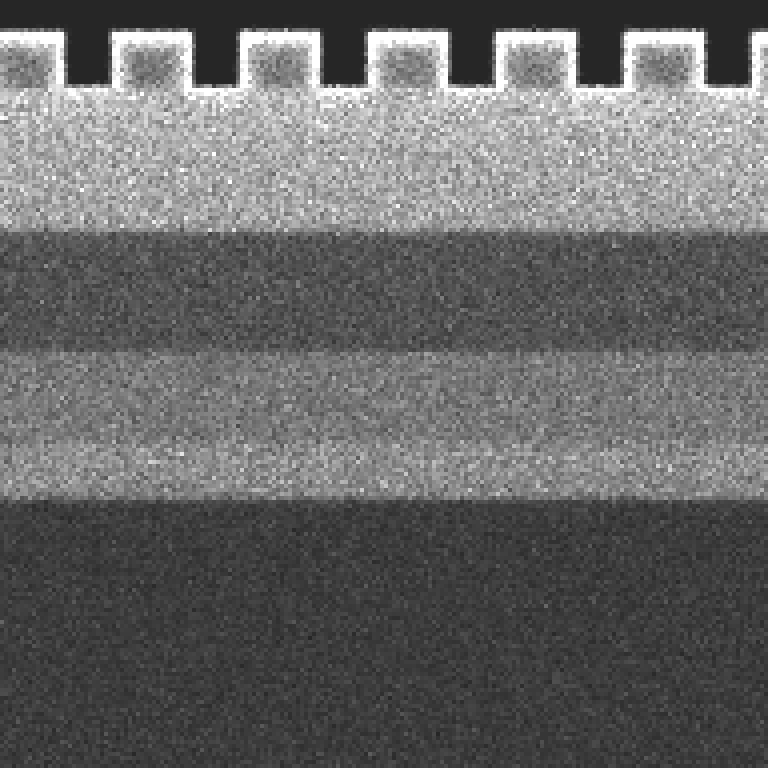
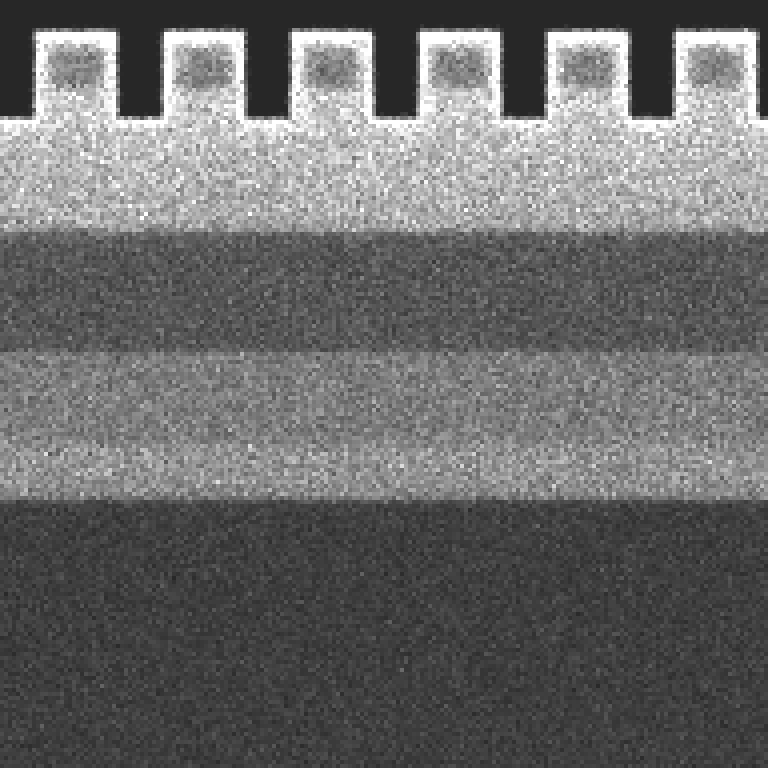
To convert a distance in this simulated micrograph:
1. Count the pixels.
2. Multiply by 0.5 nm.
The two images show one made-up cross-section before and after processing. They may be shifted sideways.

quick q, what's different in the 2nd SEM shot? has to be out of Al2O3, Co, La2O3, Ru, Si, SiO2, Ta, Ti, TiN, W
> W removed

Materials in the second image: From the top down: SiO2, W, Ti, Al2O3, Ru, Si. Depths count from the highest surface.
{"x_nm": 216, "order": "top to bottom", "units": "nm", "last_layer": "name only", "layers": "SiO2 28, W 72, Ti 60, Al2O3 46, Ru 28, Si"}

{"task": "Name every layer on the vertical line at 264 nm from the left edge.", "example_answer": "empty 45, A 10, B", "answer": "empty 44, W 56, Ti 60, Al2O3 46, Ru 28, Si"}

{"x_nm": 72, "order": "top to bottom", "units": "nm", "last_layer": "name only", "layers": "empty 44, W 56, Ti 60, Al2O3 46, Ru 28, Si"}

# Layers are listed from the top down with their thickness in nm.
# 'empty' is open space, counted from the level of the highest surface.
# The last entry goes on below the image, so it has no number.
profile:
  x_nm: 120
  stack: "SiO2 28, W 72, Ti 60, Al2O3 46, Ru 28, Si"